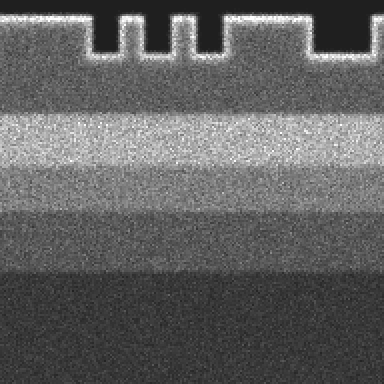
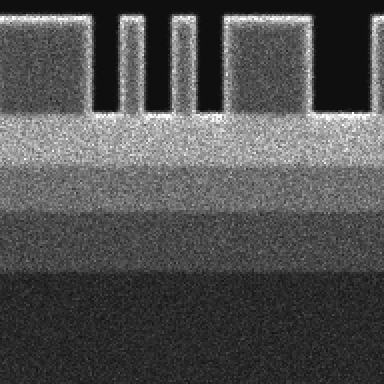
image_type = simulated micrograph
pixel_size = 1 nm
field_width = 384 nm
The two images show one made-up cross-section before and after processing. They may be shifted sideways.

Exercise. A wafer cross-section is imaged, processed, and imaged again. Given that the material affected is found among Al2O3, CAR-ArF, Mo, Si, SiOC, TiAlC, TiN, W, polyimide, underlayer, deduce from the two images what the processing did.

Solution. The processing removed underlayer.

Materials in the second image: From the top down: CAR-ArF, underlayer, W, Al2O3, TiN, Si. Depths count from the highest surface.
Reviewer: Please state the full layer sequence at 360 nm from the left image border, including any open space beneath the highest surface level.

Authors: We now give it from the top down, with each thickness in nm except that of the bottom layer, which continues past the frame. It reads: empty 98, W 52, Al2O3 46, TiN 60, Si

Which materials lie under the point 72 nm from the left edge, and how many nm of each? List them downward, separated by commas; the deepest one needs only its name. CAR-ArF 38, underlayer 60, W 52, Al2O3 46, TiN 60, Si